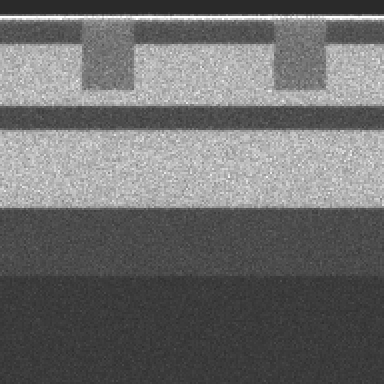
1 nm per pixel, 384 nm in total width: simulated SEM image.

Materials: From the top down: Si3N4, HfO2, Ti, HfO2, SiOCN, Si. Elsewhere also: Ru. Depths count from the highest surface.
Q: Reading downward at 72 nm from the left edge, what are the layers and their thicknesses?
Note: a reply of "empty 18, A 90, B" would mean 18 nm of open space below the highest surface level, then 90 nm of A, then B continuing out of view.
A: Si3N4 28, HfO2 62, Ti 24, HfO2 78, SiOCN 68, Si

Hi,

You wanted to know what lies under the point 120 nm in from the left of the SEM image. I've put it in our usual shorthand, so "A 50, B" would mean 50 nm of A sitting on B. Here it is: Ru 74, HfO2 16, Ti 24, HfO2 78, SiOCN 68, Si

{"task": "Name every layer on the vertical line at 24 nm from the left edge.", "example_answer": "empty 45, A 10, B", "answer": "Si3N4 28, HfO2 62, Ti 24, HfO2 78, SiOCN 68, Si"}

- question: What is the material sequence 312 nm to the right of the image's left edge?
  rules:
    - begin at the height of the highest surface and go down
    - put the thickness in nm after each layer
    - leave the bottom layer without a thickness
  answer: Ru 74, HfO2 16, Ti 24, HfO2 78, SiOCN 68, Si